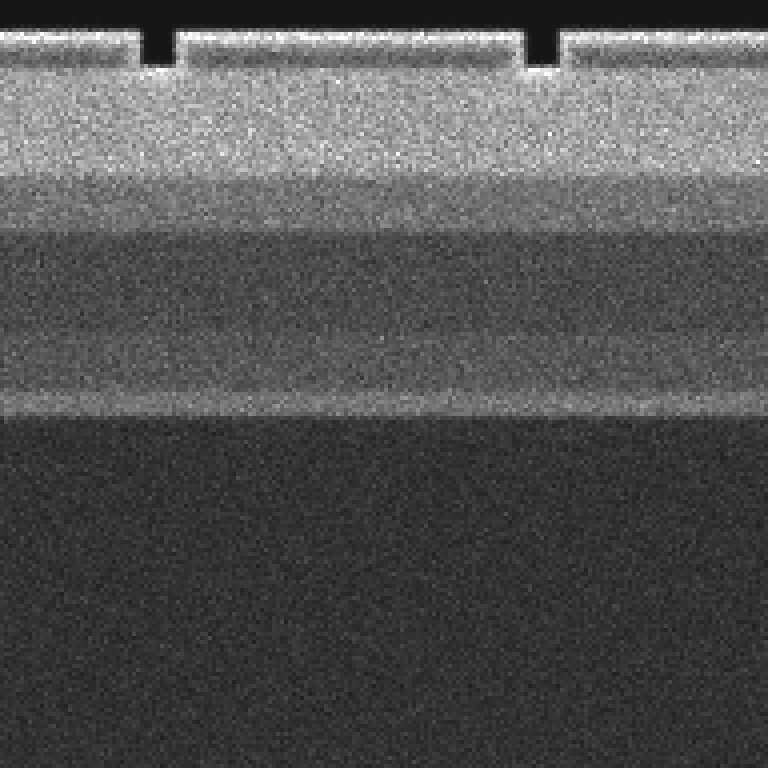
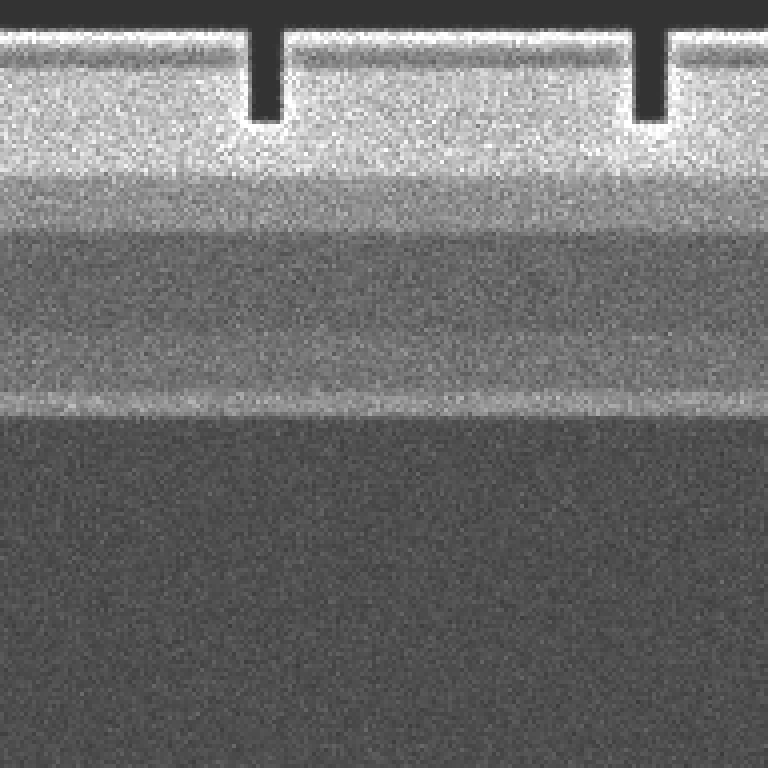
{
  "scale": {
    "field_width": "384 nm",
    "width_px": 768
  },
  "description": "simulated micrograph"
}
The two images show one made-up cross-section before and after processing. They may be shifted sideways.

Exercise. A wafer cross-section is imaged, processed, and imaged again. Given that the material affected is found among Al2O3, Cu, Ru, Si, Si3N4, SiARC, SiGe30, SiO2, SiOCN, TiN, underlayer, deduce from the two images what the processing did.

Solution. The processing removed Ru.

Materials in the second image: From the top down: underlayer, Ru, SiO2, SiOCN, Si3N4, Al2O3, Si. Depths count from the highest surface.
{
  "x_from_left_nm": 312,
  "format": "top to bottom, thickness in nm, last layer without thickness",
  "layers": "underlayer 18, Ru 54, SiO2 28, SiOCN 50, Si3N4 30, Al2O3 12, Si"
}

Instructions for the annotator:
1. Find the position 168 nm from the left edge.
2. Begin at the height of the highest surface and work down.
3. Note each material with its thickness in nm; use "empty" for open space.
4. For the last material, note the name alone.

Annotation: underlayer 18, Ru 54, SiO2 28, SiOCN 50, Si3N4 30, Al2O3 12, Si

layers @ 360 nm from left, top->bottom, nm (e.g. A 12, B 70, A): underlayer 18, Ru 54, SiO2 28, SiOCN 50, Si3N4 30, Al2O3 12, Si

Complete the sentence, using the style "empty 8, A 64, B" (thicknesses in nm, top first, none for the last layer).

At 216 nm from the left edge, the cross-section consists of underlayer 18, Ru 54, SiO2 28, SiOCN 50, Si3N4 30, Al2O3 12, Si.